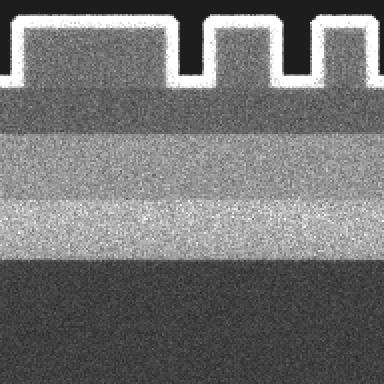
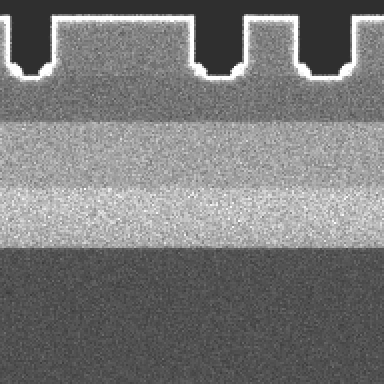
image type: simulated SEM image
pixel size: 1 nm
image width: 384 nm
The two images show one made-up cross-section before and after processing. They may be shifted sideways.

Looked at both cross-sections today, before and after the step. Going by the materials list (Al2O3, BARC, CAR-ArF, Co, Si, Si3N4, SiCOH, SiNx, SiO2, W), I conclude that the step removed W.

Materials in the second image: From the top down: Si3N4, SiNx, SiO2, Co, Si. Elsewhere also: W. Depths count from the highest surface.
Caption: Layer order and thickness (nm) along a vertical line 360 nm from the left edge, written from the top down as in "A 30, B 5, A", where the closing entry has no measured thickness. Si3N4 60, SiNx 46, SiO2 66, Co 60, Si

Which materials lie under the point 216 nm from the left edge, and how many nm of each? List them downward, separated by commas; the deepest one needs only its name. empty 60, SiNx 46, SiO2 66, Co 60, Si